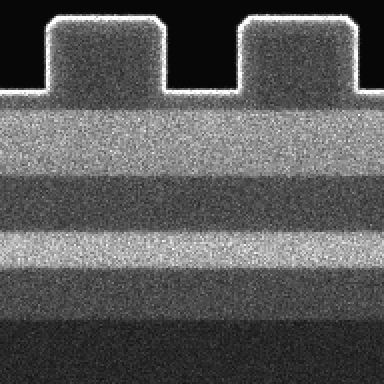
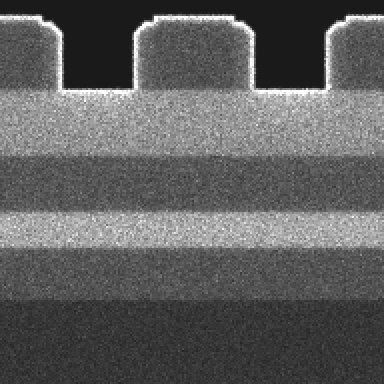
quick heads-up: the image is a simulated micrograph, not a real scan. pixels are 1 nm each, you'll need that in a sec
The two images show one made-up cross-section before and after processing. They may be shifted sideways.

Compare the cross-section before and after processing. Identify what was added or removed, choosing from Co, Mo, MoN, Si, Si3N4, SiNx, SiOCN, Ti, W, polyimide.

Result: Si3N4 removed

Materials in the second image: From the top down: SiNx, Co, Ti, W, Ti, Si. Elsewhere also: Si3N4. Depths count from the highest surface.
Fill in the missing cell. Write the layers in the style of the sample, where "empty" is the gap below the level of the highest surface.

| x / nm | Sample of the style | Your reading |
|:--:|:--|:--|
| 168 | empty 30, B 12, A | SiNx 74, Co 66, Ti 56, W 36, Ti 52, Si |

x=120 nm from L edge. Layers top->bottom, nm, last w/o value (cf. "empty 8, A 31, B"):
empty 74, Co 66, Ti 56, W 36, Ti 52, Si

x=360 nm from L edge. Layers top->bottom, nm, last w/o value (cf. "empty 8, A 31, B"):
SiNx 74, Co 66, Ti 56, W 36, Ti 52, Si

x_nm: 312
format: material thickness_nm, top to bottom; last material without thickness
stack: empty 74, Co 66, Ti 56, W 36, Ti 52, Si